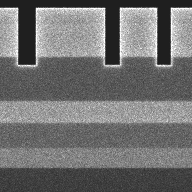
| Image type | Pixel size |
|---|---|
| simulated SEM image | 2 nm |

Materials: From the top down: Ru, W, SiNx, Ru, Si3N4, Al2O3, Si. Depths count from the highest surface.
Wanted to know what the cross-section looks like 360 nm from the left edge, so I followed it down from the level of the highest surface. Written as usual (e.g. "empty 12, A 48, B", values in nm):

Ru 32, W 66, SiNx 88, Ru 44, Si3N4 50, Al2O3 40, Si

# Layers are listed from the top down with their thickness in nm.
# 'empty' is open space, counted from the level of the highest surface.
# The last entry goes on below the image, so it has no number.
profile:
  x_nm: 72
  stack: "Ru 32, W 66, SiNx 88, Ru 44, Si3N4 50, Al2O3 40, Si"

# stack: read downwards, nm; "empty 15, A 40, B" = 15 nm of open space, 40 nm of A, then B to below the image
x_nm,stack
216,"empty 114, SiNx 72, Ru 44, Si3N4 50, Al2O3 40, Si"